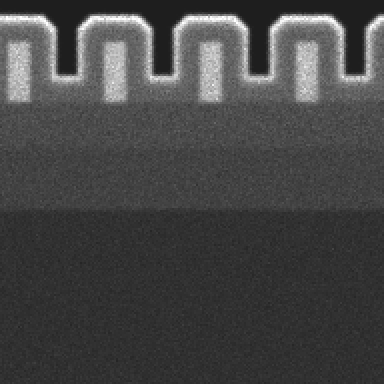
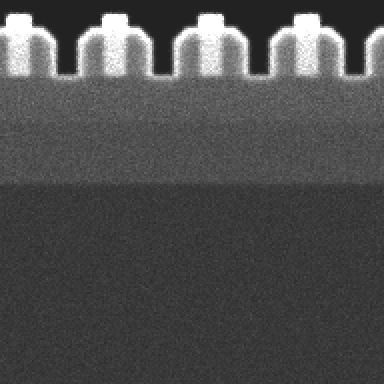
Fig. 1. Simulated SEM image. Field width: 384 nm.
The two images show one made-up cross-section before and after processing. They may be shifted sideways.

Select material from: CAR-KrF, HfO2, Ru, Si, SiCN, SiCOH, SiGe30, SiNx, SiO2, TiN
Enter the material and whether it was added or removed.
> SiO2 / removed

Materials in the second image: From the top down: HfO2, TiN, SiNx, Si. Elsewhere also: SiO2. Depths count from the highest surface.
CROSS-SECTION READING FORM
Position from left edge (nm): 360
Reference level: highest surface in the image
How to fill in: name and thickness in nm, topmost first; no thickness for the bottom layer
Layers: empty 60, TiN 46, SiNx 62, Si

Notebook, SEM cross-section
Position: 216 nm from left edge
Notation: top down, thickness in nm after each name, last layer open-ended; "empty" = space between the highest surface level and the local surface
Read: HfO2 60, TiN 46, SiNx 62, Si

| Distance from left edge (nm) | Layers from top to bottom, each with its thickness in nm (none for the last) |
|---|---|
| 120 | HfO2 60, TiN 46, SiNx 62, Si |